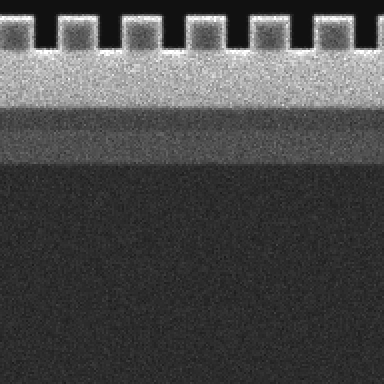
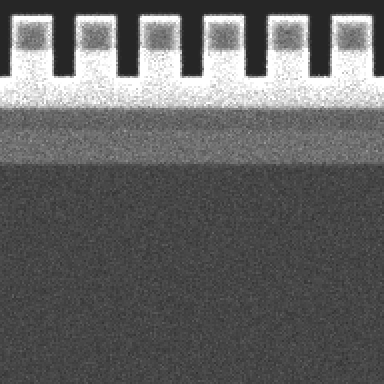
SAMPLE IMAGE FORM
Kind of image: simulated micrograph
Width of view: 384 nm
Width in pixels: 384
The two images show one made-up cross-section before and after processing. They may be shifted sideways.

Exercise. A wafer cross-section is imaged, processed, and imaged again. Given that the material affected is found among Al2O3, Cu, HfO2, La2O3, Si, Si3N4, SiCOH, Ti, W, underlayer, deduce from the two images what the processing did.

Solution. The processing removed W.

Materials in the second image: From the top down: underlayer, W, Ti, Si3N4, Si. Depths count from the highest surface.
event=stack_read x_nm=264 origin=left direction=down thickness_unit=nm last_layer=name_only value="empty 62, W 30, Ti 22, Si3N4 34, Si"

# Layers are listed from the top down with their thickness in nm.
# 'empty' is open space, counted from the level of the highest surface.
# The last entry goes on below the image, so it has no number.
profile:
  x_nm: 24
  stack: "underlayer 34, W 58, Ti 22, Si3N4 34, Si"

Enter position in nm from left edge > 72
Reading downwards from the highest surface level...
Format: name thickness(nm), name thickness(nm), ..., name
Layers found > empty 62, W 30, Ti 22, Si3N4 34, Si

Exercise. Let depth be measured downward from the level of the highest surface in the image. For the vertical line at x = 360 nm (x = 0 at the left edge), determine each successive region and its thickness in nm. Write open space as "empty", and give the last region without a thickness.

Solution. underlayer 34, W 58, Ti 22, Si3N4 34, Si